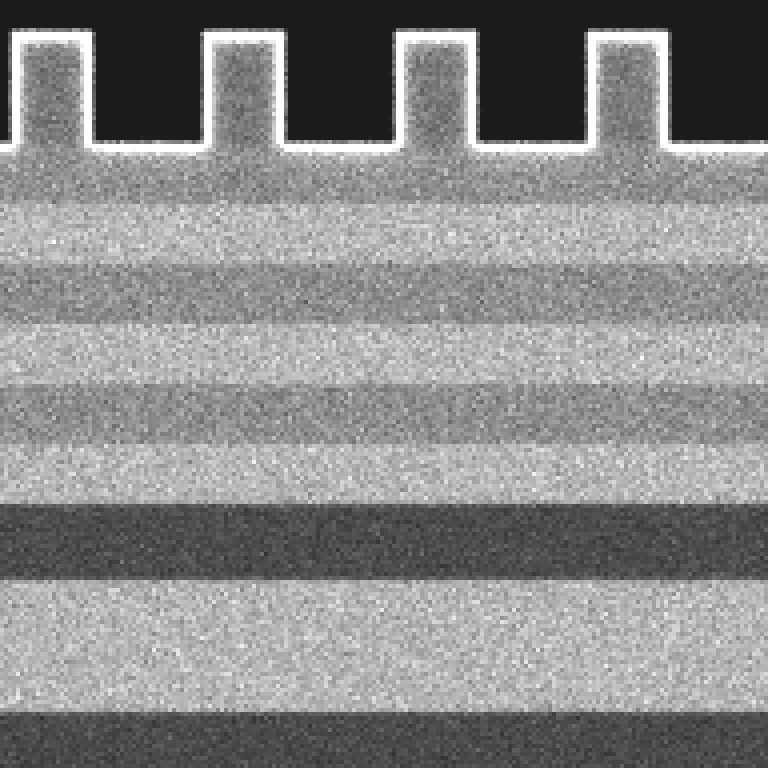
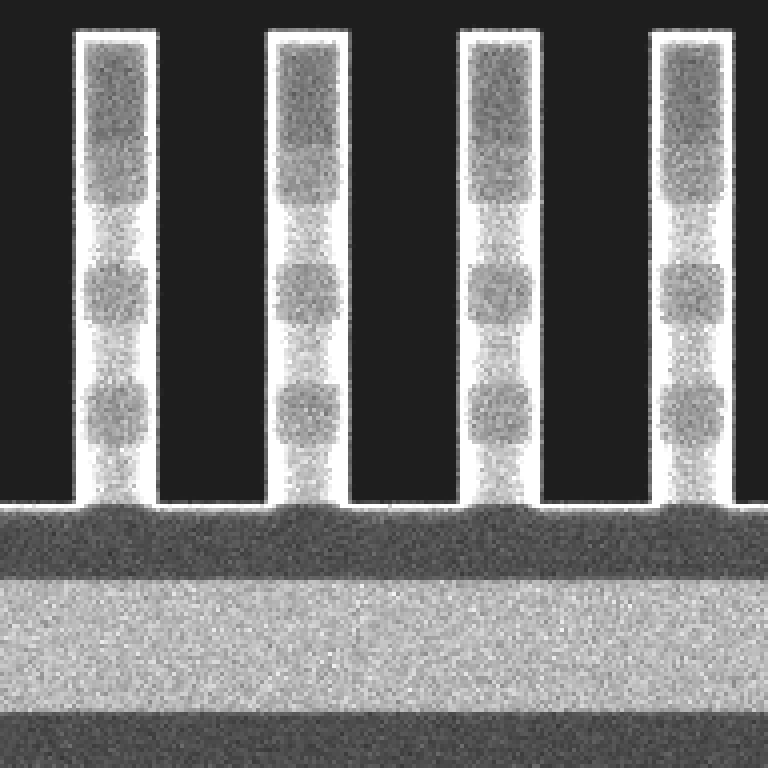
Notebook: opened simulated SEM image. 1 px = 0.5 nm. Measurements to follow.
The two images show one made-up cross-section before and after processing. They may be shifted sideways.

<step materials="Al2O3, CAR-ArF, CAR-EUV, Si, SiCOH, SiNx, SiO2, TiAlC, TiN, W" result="removed SiO2 and TiN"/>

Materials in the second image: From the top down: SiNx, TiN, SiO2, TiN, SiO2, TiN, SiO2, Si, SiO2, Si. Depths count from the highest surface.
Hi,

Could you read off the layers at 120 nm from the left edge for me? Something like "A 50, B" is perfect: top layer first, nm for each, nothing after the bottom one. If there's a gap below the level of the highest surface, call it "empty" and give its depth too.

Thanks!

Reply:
empty 236, Si 38, SiO2 66, Si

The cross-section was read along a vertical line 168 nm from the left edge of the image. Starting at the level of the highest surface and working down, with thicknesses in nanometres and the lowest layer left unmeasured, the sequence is SiNx 56, TiN 30, SiO2 30, TiN 30, SiO2 30, TiN 30, SiO2 30, Si 38, SiO2 66, Si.